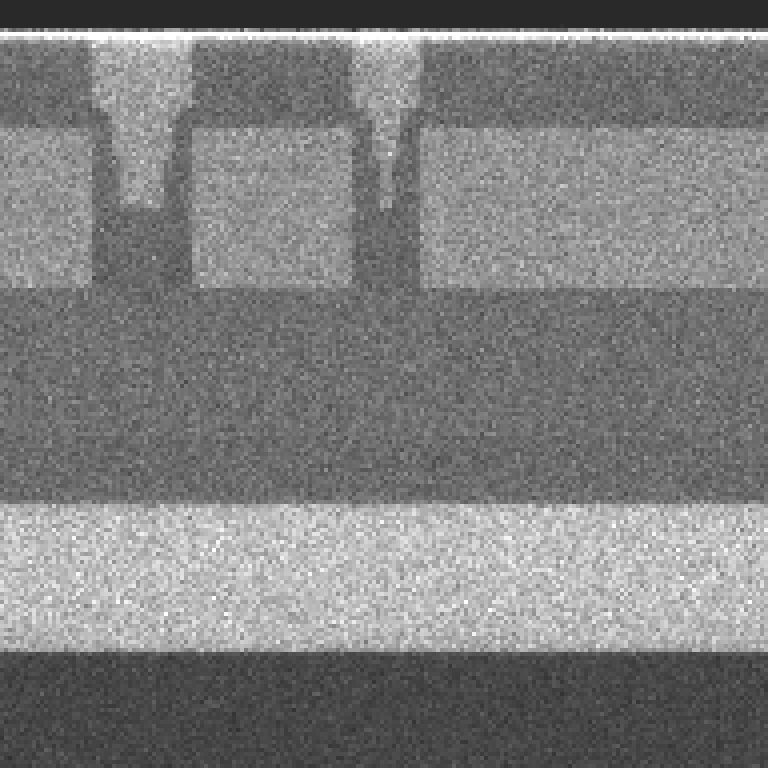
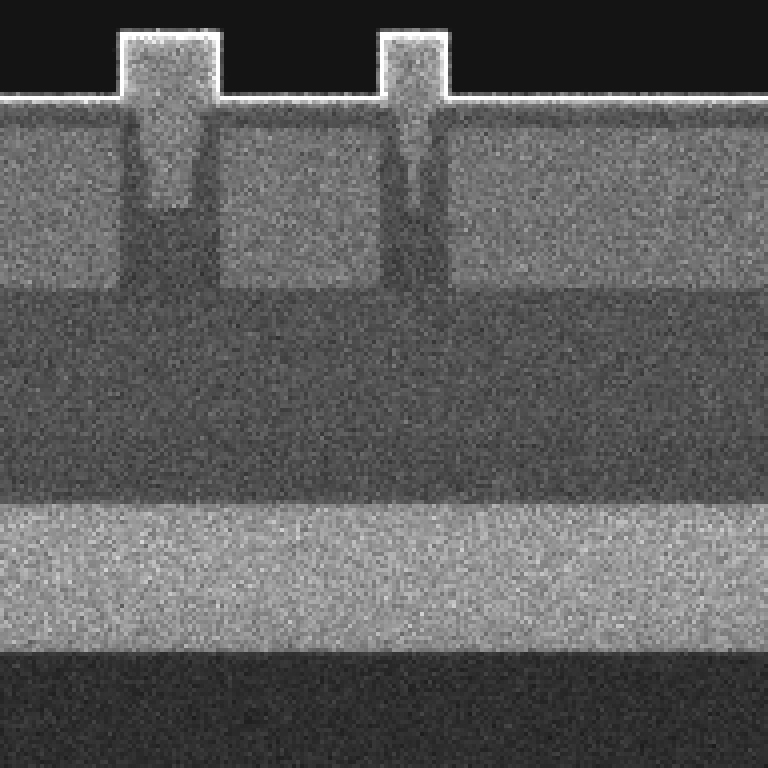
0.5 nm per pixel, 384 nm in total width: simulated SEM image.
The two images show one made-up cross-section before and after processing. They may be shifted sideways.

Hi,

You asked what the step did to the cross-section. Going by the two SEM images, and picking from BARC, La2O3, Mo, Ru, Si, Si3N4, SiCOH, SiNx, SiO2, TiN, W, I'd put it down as TiN, removed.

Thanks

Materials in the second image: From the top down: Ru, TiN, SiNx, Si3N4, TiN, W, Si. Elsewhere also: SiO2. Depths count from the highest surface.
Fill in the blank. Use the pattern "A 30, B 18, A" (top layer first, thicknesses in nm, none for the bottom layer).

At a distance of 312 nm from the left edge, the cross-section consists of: empty 32, TiN 16, SiO2 80, Si3N4 74, TiN 34, W 74, Si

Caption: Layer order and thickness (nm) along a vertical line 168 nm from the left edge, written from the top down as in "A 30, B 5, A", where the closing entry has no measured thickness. empty 32, TiN 16, SiO2 80, Si3N4 74, TiN 34, W 74, Si